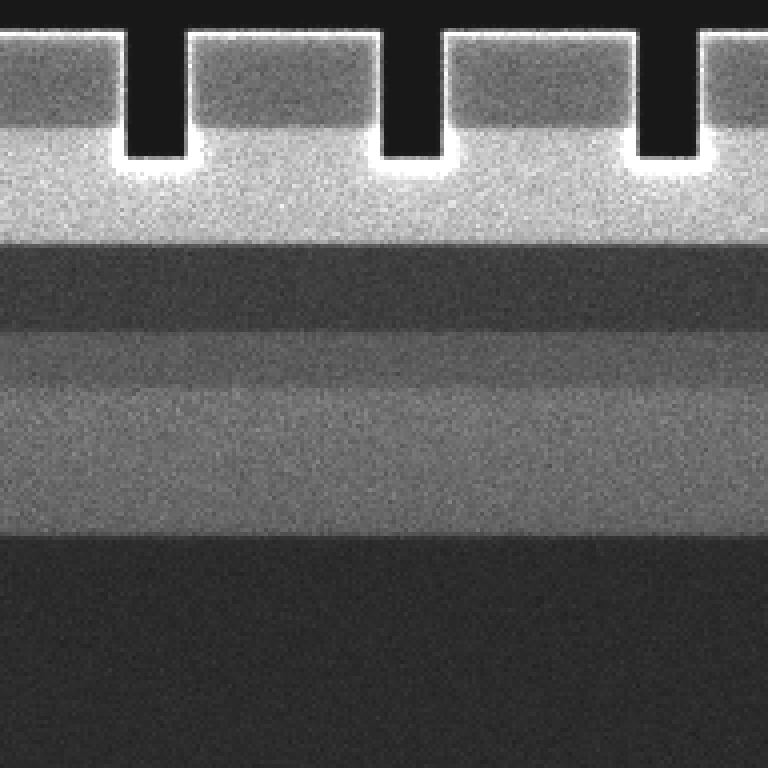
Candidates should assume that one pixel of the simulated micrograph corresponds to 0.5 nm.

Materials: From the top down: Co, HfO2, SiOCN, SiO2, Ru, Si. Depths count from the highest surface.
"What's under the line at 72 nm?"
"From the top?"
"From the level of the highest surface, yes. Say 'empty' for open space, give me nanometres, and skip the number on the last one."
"empty 64, HfO2 42, SiOCN 44, SiO2 28, Ru 74, Si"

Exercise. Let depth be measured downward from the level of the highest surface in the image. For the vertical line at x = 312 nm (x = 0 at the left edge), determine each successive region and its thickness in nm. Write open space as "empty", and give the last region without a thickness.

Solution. Co 48, HfO2 58, SiOCN 44, SiO2 28, Ru 74, Si